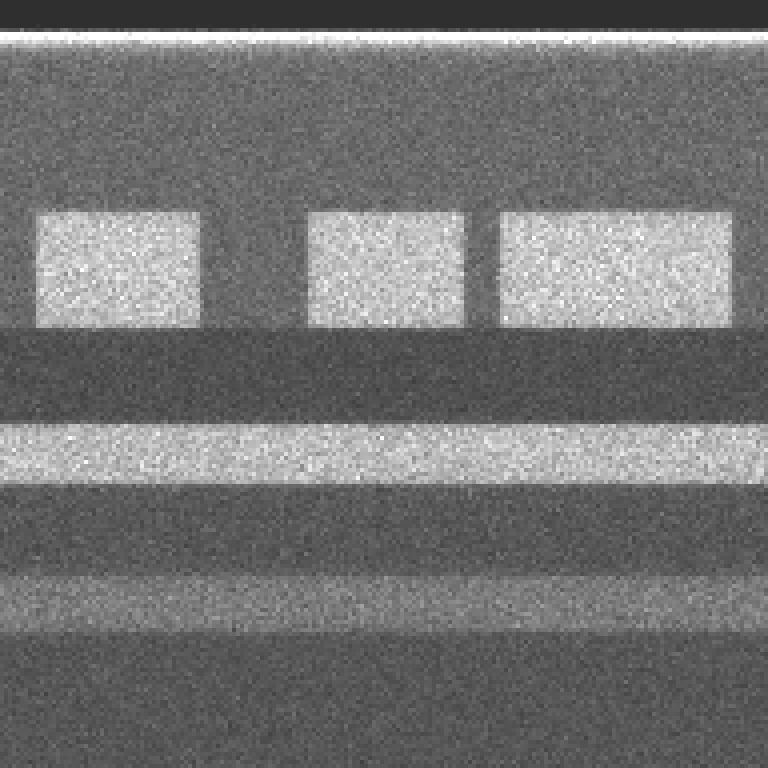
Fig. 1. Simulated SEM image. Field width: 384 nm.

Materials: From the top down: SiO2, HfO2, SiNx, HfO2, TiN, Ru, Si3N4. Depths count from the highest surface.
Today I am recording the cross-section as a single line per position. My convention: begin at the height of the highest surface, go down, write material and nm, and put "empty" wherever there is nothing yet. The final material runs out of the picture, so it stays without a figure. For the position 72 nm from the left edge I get SiO2 90, HfO2 58, SiNx 48, HfO2 30, TiN 46, Ru 28, Si3N4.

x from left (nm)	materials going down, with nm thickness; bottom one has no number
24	SiO2 90, HfO2 58, SiNx 48, HfO2 30, TiN 46, Ru 28, Si3N4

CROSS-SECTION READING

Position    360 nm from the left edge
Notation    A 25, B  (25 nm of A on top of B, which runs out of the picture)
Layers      SiO2 90, HfO2 58, SiNx 48, HfO2 30, TiN 46, Ru 28, Si3N4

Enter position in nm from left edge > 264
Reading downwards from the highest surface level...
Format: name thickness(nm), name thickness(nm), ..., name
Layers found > SiO2 90, HfO2 58, SiNx 48, HfO2 30, TiN 46, Ru 28, Si3N4